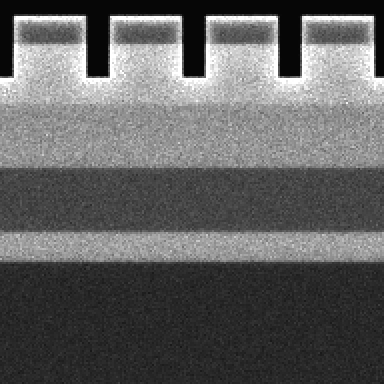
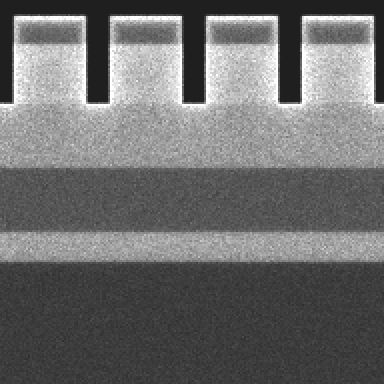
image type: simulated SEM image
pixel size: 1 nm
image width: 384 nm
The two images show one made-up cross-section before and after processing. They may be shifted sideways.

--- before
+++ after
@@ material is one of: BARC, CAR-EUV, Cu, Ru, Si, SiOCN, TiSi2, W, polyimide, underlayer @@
W removed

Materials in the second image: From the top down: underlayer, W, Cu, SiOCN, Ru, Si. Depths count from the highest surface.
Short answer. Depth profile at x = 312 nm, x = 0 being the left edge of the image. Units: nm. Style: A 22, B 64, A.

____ underlayer 28, W 60, Cu 64, SiOCN 64, Ru 30, Si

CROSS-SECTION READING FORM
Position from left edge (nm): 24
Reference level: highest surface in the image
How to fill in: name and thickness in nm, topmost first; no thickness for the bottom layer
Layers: underlayer 28, W 60, Cu 64, SiOCN 64, Ru 30, Si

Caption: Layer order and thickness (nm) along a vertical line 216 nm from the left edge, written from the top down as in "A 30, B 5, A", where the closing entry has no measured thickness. underlayer 28, W 60, Cu 64, SiOCN 64, Ru 30, Si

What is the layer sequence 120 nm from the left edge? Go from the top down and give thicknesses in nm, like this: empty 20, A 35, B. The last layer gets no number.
underlayer 28, W 60, Cu 64, SiOCN 64, Ru 30, Si